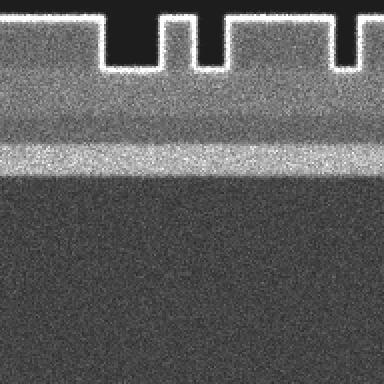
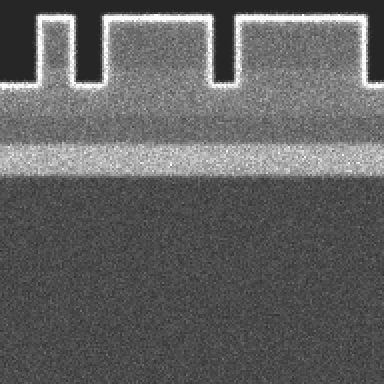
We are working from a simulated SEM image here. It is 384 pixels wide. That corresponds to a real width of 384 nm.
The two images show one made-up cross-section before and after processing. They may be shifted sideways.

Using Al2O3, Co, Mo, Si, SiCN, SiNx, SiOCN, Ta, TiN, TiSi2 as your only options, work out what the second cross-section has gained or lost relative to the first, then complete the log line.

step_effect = removed TiN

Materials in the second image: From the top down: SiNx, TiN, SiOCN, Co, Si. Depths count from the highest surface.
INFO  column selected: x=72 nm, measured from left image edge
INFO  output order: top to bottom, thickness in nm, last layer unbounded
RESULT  SiNx 52, TiN 48, SiOCN 28, Co 32, Si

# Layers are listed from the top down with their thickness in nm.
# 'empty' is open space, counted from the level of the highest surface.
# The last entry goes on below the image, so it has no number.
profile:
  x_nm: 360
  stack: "SiNx 52, TiN 48, SiOCN 28, Co 32, Si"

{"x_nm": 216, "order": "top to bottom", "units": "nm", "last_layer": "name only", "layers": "empty 68, TiN 32, SiOCN 28, Co 32, Si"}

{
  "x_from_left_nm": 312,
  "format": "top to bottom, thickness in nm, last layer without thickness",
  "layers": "SiNx 52, TiN 48, SiOCN 28, Co 32, Si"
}